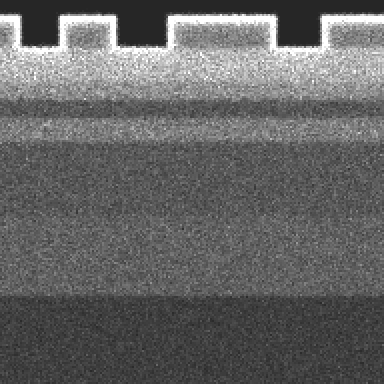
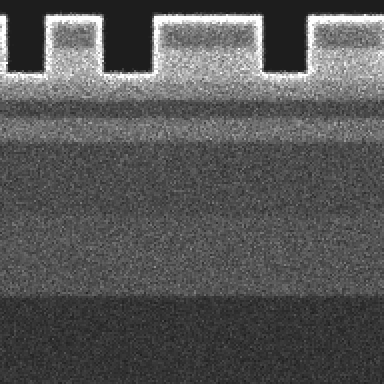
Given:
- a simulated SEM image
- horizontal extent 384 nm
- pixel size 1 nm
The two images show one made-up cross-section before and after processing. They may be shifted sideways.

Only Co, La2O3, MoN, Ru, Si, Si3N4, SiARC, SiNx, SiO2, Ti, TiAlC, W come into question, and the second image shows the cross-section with W removed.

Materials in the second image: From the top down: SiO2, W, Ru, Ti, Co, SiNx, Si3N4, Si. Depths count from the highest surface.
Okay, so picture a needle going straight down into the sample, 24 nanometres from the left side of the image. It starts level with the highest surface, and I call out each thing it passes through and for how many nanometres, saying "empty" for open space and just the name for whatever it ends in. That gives empty 58, W 8, Ru 18, Ti 18, Co 24, SiNx 74, Si3N4 80, Si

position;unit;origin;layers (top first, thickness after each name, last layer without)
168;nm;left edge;SiO2 32, W 34, Ru 18, Ti 18, Co 24, SiNx 74, Si3N4 80, Si